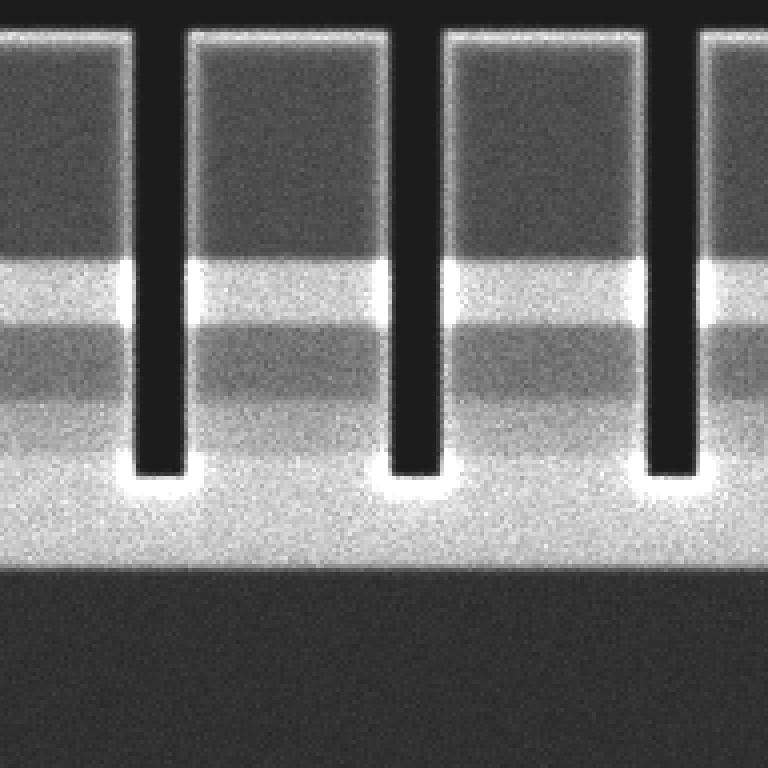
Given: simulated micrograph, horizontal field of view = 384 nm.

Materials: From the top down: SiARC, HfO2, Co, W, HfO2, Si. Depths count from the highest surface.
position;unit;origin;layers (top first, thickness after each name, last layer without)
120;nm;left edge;SiARC 114, HfO2 32, Co 38, W 28, HfO2 56, Si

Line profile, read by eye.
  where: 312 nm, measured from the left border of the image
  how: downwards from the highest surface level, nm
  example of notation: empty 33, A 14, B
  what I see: SiARC 114, HfO2 32, Co 38, W 28, HfO2 56, Si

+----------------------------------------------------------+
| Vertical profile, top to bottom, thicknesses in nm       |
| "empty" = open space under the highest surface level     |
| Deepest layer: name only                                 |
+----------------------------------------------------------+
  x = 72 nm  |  empty 224, HfO2 44, Si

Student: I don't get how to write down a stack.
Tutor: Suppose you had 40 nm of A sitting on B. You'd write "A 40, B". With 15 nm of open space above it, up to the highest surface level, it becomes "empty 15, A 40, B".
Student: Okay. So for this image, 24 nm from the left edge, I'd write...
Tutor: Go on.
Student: SiARC 114, HfO2 32, Co 38, W 28, HfO2 56, Si